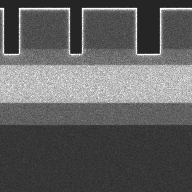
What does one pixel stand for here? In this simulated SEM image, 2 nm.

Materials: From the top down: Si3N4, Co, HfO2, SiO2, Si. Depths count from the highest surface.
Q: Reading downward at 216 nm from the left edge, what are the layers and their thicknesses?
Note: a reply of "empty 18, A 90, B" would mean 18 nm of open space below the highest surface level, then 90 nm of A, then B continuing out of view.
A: Si3N4 82, Co 32, HfO2 76, SiO2 44, Si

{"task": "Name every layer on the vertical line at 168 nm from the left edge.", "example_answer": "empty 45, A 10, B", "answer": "Si3N4 82, Co 32, HfO2 76, SiO2 44, Si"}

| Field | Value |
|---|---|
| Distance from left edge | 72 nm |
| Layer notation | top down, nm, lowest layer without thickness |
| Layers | Si3N4 82, Co 32, HfO2 76, SiO2 44, Si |